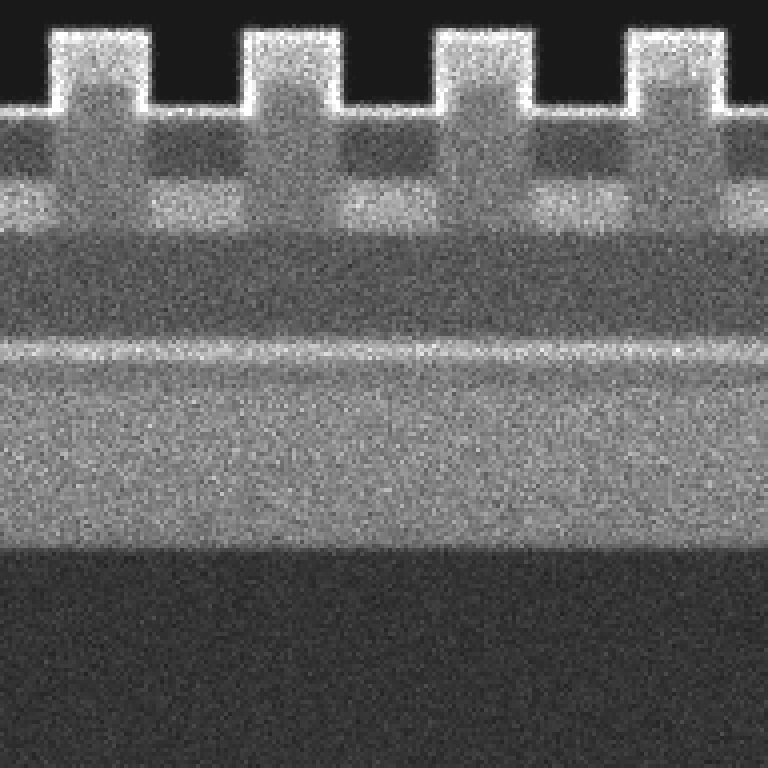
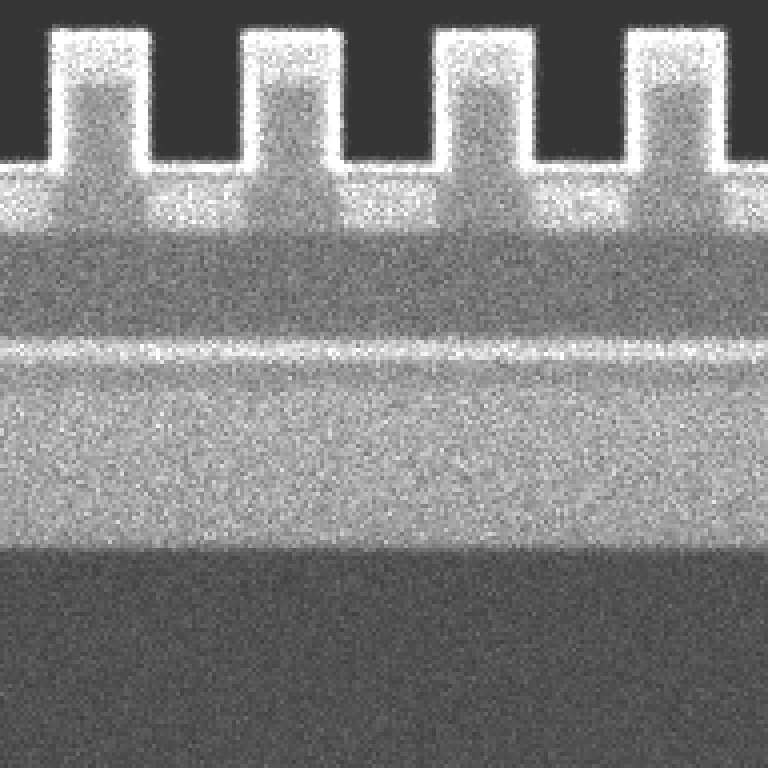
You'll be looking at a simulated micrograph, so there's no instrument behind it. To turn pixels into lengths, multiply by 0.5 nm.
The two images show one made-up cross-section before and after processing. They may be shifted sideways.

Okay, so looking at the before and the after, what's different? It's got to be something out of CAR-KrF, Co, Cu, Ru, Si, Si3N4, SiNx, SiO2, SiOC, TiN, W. SiNx, removed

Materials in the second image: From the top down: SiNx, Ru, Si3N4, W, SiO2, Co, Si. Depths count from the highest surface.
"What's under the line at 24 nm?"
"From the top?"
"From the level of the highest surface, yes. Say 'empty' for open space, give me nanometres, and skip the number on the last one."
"empty 66, SiNx 8, Ru 26, Si3N4 54, W 10, SiO2 14, Co 80, Si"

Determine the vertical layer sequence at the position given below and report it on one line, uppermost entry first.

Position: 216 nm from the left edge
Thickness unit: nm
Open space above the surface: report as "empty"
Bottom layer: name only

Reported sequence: empty 66, SiNx 8, Ru 26, Si3N4 54, W 10, SiO2 14, Co 80, Si